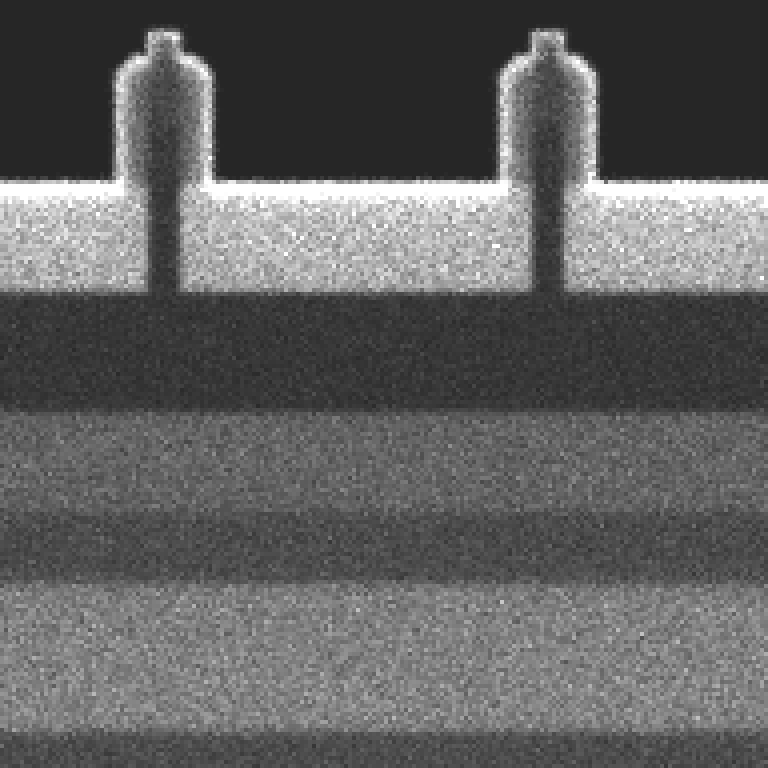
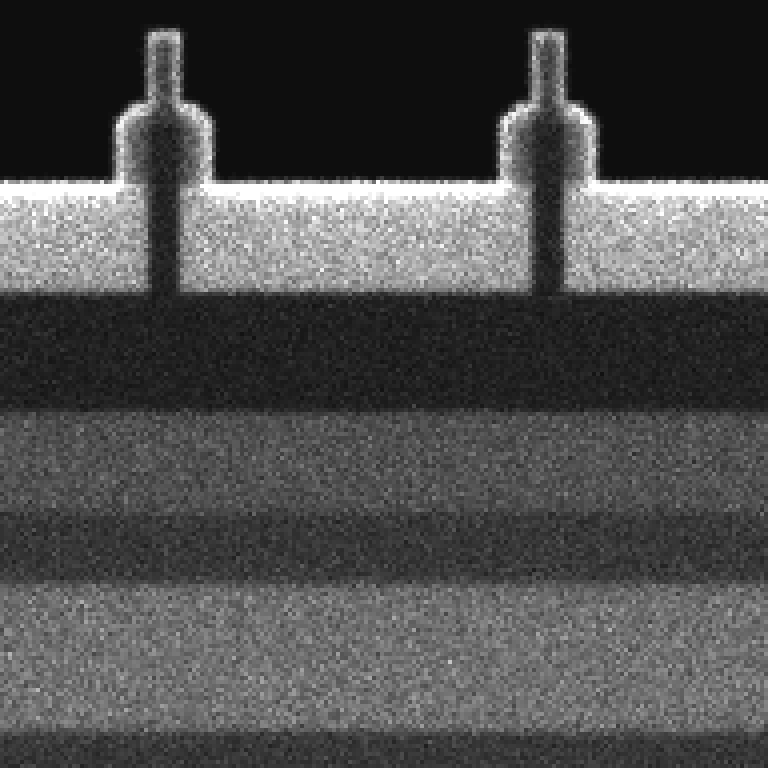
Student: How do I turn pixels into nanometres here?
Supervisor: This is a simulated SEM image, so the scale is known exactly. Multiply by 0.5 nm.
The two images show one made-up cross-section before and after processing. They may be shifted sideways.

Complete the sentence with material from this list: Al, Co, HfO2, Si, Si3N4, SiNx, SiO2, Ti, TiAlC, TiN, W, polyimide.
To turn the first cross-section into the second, SiO2 must be removed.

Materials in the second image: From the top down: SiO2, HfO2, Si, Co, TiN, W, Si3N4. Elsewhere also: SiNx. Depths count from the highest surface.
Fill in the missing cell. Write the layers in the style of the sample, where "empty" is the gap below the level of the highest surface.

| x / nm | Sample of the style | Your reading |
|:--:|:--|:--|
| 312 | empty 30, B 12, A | empty 76, HfO2 54, Si 60, Co 50, TiN 36, W 74, Si3N4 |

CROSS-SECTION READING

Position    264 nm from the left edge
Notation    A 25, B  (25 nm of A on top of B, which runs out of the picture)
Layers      empty 36, SiO2 40, HfO2 54, Si 60, Co 50, TiN 36, W 74, Si3N4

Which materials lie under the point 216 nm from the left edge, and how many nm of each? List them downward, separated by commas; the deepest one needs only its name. empty 76, HfO2 54, Si 60, Co 50, TiN 36, W 74, Si3N4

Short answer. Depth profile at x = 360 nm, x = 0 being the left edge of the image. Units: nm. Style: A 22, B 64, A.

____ empty 76, HfO2 54, Si 60, Co 50, TiN 36, W 74, Si3N4